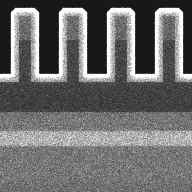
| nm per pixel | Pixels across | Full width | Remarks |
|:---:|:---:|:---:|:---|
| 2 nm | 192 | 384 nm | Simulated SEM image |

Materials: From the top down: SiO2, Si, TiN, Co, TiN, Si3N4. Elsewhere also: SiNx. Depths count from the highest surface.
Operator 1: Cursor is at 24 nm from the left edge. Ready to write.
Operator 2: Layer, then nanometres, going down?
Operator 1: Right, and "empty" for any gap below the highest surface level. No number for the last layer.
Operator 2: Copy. empty 6, SiO2 142, Si 60, TiN 38, Co 30, TiN 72, Si3N4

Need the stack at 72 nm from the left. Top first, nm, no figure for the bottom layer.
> empty 4, SiO2 144, Si 60, TiN 38, Co 30, TiN 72, Si3N4